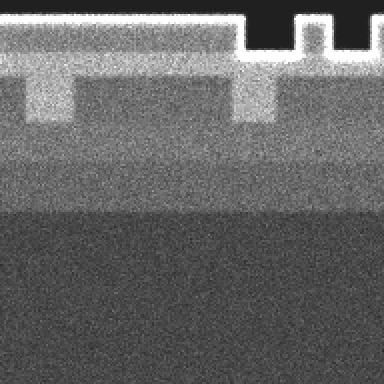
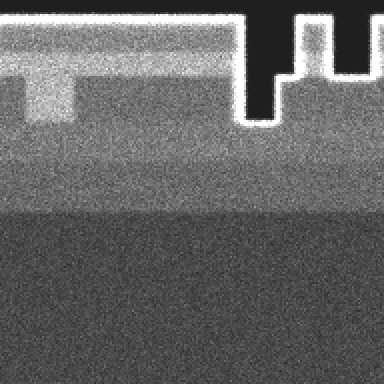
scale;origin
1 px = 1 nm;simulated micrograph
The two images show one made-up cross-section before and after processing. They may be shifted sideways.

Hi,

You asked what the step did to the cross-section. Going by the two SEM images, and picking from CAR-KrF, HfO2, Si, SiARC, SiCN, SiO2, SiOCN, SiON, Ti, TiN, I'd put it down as SiO2, removed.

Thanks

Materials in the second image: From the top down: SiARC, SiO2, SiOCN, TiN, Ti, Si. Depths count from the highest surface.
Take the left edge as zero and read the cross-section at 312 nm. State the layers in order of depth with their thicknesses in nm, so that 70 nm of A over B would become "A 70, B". SiARC 36, SiO2 24, SiOCN 46, TiN 40, Ti 50, Si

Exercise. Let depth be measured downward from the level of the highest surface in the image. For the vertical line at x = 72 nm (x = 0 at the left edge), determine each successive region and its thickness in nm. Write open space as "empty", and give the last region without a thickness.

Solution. SiARC 36, SiO2 70, TiN 40, Ti 50, Si